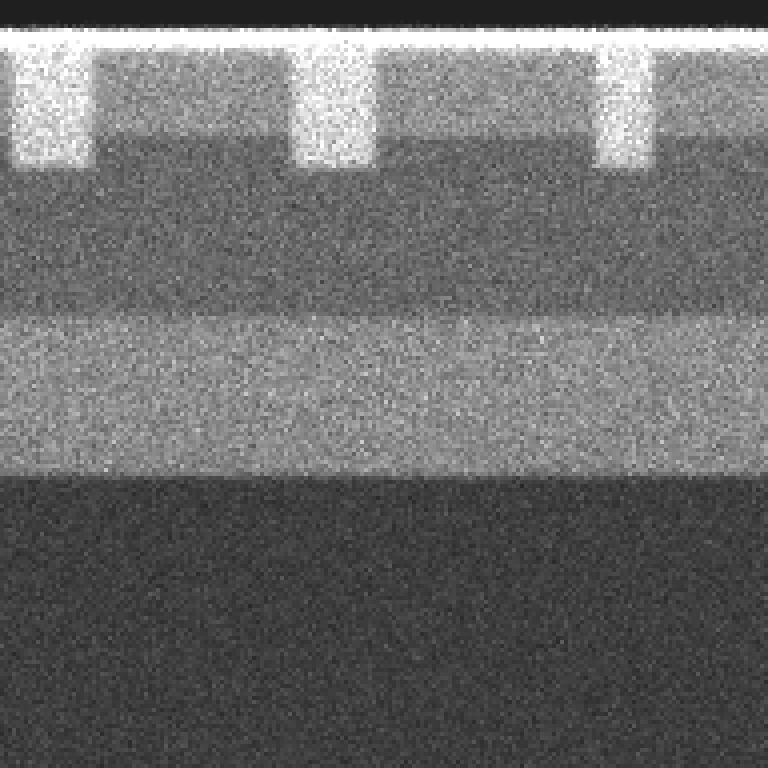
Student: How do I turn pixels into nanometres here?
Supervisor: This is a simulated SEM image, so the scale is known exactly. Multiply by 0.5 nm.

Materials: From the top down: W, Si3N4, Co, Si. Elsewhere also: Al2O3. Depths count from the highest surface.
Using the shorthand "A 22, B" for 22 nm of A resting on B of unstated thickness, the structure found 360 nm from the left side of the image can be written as Al2O3 52, Si3N4 90, Co 80, Si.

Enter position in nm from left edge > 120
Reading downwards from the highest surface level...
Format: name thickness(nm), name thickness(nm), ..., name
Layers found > Al2O3 52, Si3N4 90, Co 80, Si